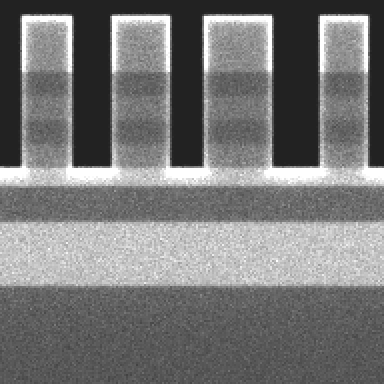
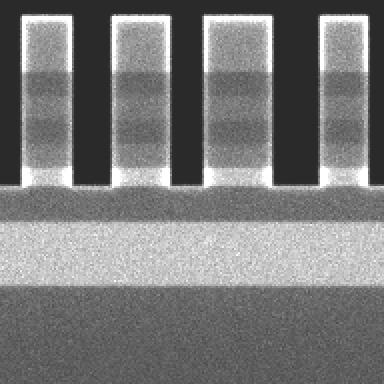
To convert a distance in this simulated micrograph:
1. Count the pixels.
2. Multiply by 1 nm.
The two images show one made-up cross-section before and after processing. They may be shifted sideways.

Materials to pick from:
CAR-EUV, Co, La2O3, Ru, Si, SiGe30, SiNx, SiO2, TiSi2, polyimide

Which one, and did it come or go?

SiO2 - removed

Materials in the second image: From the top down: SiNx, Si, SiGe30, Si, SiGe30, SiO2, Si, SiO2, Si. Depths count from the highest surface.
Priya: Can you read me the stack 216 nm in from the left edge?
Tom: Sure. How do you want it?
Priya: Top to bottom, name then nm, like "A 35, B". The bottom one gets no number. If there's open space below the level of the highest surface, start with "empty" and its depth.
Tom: SiNx 56, Si 24, SiGe30 24, Si 24, SiGe30 24, SiO2 18, Si 36, SiO2 64, Si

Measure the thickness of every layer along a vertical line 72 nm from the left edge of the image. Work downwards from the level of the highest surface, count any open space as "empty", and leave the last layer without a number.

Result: empty 170, Si 36, SiO2 64, Si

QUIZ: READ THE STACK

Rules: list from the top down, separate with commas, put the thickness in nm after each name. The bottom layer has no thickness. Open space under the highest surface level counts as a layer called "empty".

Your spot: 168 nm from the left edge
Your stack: SiNx 56, Si 24, SiGe30 24, Si 24, SiGe30 24, SiO2 18, Si 36, SiO2 64, Si